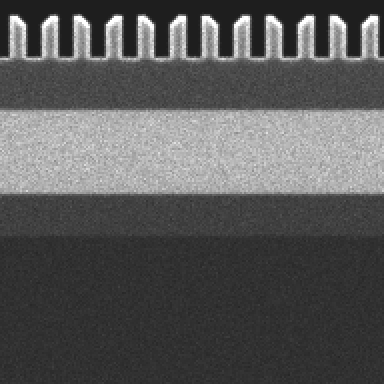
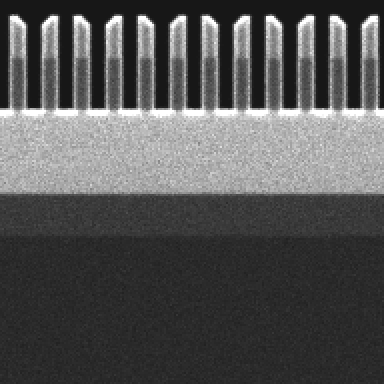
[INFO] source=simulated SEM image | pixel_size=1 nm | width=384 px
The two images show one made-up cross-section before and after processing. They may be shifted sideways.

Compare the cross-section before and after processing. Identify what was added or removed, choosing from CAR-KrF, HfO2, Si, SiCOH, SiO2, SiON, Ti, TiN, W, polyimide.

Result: TiN removed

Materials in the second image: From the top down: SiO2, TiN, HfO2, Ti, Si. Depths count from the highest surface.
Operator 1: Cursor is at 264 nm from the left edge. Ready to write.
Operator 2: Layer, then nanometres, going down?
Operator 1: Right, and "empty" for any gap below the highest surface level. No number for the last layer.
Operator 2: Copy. empty 94, HfO2 84, Ti 42, Si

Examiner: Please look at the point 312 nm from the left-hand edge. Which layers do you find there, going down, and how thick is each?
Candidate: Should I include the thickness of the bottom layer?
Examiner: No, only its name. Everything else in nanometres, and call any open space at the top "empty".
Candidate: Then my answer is SiO2 42, TiN 52, HfO2 84, Ti 42, Si